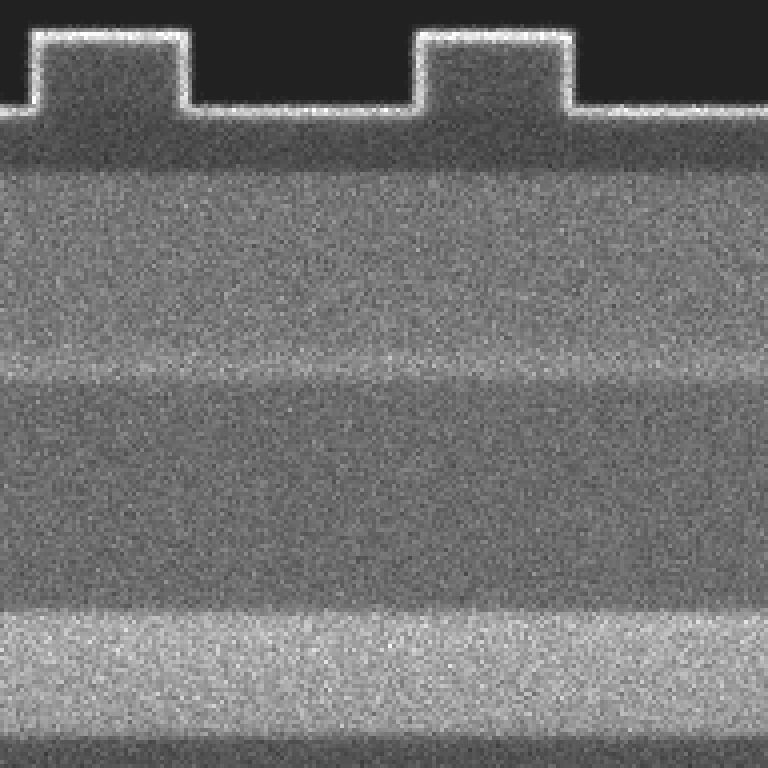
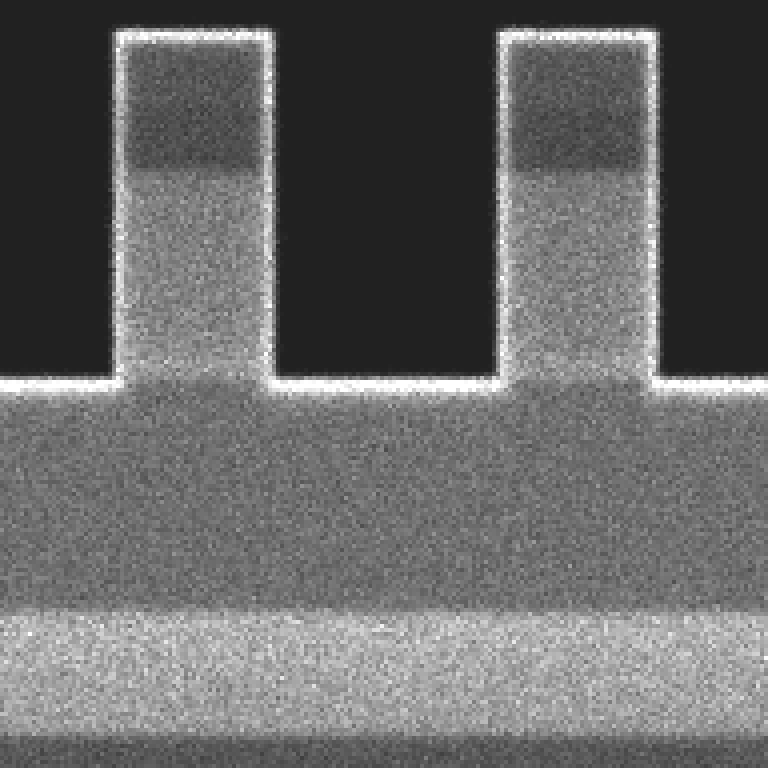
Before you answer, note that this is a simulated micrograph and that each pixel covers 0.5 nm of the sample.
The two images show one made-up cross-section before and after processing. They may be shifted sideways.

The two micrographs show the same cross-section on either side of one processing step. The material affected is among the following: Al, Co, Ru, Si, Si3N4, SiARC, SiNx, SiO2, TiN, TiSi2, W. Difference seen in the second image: Co and Ru and SiNx removed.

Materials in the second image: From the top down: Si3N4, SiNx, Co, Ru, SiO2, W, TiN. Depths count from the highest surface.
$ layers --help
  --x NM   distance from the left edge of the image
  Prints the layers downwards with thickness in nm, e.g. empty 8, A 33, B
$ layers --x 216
empty 174, SiO2 116, W 62, TiN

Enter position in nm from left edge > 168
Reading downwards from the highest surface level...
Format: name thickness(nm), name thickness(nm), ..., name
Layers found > empty 174, SiO2 116, W 62, TiN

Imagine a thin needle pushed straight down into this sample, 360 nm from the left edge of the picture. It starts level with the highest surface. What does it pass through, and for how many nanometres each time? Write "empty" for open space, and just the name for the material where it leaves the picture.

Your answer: empty 174, SiO2 116, W 62, TiN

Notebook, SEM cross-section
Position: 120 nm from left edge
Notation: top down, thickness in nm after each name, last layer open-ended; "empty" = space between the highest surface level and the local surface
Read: Si3N4 38, SiNx 32, Co 90, Ru 14, SiO2 116, W 62, TiN